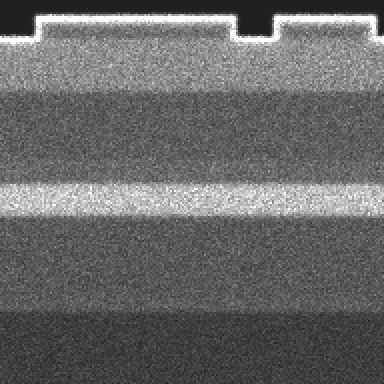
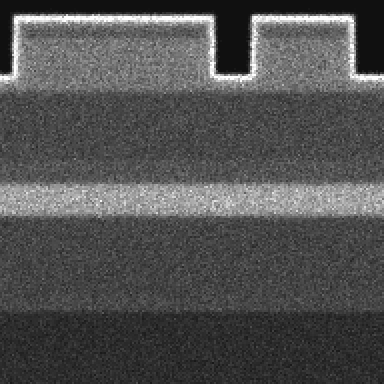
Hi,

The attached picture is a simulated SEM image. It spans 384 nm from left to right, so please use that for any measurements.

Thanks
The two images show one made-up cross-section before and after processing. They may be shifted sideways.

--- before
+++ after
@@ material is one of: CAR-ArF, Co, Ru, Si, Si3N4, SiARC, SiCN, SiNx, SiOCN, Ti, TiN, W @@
Co removed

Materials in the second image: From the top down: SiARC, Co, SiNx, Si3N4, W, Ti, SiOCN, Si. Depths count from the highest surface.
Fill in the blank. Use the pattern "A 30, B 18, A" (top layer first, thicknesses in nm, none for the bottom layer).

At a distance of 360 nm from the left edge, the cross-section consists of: empty 60, Co 16, SiNx 68, Si3N4 24, W 32, Ti 80, SiOCN 16, Si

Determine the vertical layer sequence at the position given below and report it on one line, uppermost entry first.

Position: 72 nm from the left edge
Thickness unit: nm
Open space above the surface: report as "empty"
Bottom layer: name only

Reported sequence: SiARC 22, Co 54, SiNx 68, Si3N4 24, W 32, Ti 80, SiOCN 16, Si